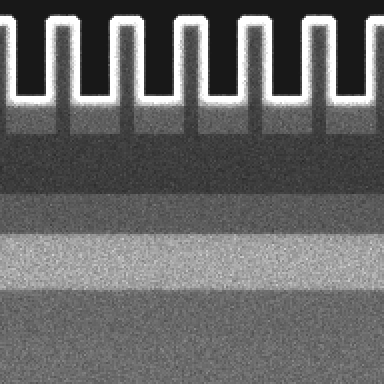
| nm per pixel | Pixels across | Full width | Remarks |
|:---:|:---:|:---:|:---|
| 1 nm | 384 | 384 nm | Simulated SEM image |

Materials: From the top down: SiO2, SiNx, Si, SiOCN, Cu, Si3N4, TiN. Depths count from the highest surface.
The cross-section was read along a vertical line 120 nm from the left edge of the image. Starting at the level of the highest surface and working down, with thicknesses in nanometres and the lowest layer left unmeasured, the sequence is SiO2 10, Si 168, SiOCN 40, Cu 56, Si3N4 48, TiN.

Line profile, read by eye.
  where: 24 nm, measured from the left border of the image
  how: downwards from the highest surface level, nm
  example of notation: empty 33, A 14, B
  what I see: empty 80, SiO2 10, SiNx 28, Si 60, SiOCN 40, Cu 56, Si3N4 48, TiN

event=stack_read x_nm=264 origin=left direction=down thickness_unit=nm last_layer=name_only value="SiO2 90, SiNx 28, Si 60, SiOCN 40, Cu 56, Si3N4 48, TiN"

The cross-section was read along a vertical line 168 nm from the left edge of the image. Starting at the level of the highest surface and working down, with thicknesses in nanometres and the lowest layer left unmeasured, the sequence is empty 80, SiO2 10, SiNx 28, Si 60, SiOCN 40, Cu 56, Si3N4 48, TiN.